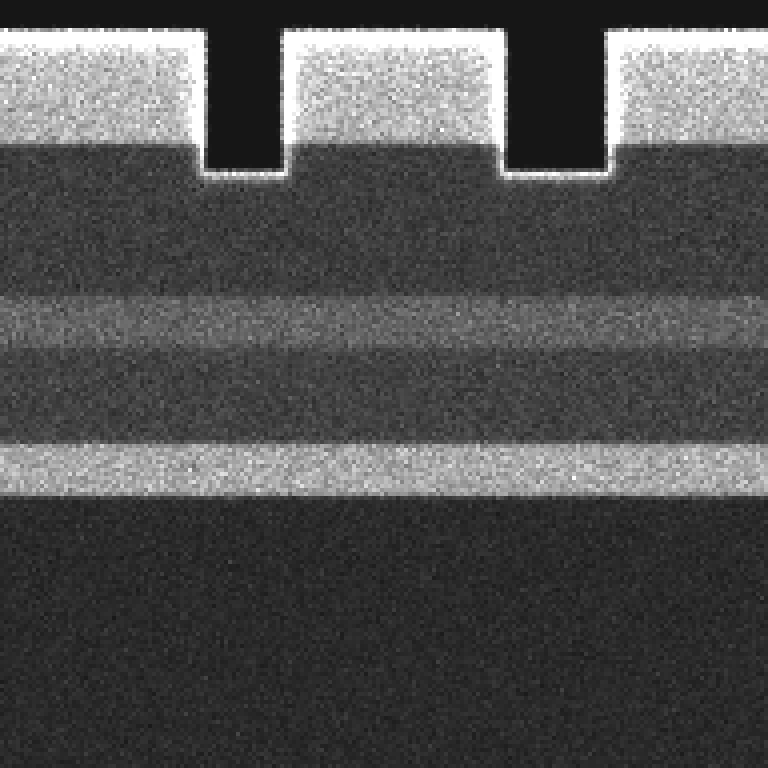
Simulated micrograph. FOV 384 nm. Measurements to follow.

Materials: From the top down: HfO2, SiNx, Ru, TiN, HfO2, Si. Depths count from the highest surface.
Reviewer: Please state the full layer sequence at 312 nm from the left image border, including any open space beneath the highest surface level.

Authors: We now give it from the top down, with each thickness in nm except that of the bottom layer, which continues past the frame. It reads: HfO2 56, SiNx 76, Ru 26, TiN 48, HfO2 26, Si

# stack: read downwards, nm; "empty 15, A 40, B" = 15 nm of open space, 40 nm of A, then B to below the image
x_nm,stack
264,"empty 70, SiNx 62, Ru 26, TiN 48, HfO2 26, Si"